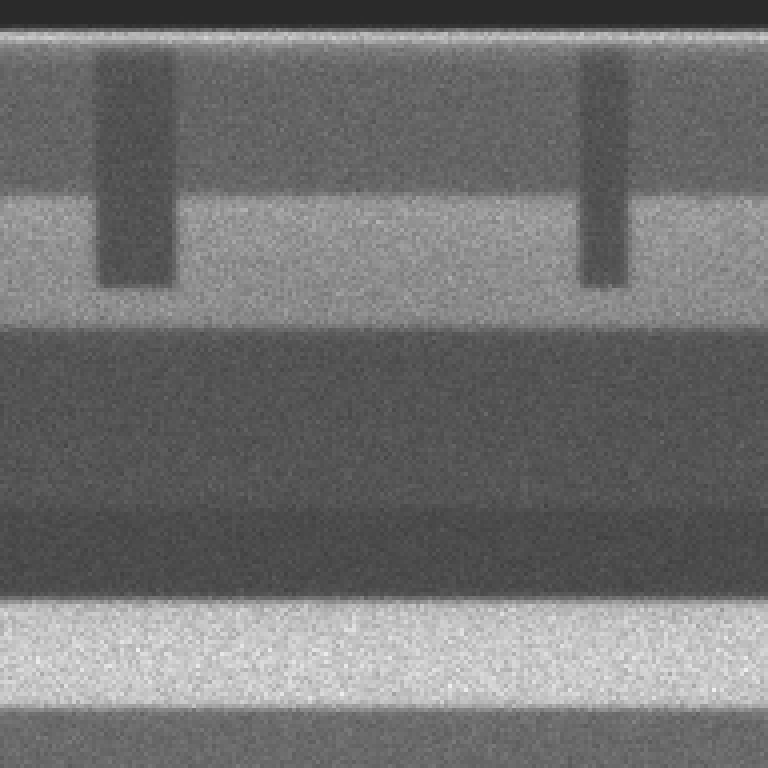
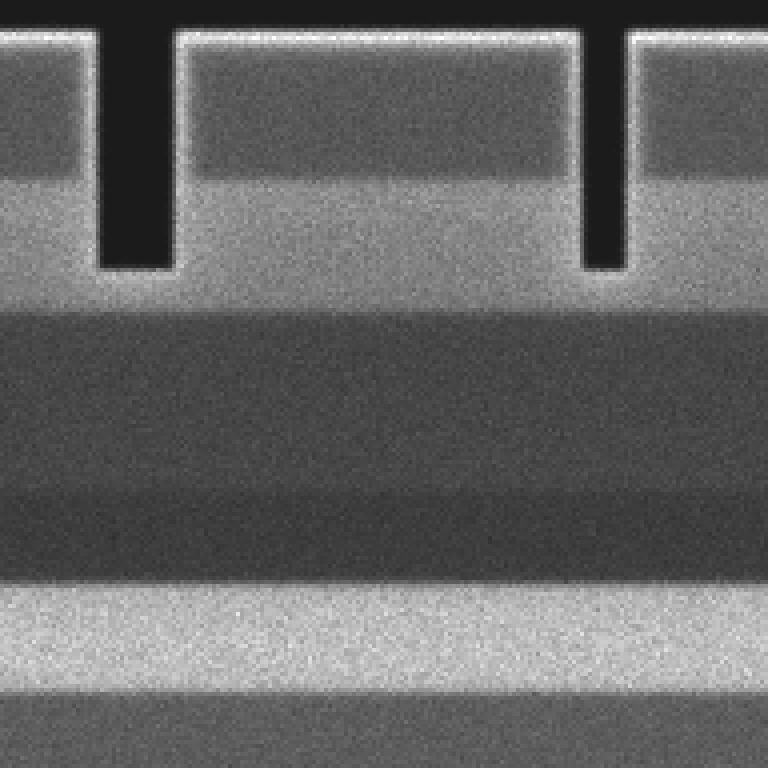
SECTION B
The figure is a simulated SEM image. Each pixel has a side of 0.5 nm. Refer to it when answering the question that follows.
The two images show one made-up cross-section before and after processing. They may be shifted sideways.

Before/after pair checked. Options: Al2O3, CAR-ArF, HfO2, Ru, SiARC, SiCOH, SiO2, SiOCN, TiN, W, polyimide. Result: removed SiARC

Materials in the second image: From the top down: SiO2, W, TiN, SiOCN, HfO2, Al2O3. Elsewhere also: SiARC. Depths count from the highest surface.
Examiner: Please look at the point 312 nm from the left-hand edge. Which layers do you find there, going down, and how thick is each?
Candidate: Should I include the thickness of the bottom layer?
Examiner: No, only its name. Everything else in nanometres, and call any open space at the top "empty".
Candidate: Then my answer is empty 120, W 20, TiN 90, SiOCN 46, HfO2 54, Al2O3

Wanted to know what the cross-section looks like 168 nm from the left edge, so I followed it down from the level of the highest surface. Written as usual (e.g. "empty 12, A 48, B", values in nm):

SiO2 74, W 66, TiN 90, SiOCN 46, HfO2 54, Al2O3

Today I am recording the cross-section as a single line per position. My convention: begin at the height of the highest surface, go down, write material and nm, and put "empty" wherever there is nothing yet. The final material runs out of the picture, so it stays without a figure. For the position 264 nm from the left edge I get SiO2 74, W 66, TiN 90, SiOCN 46, HfO2 54, Al2O3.